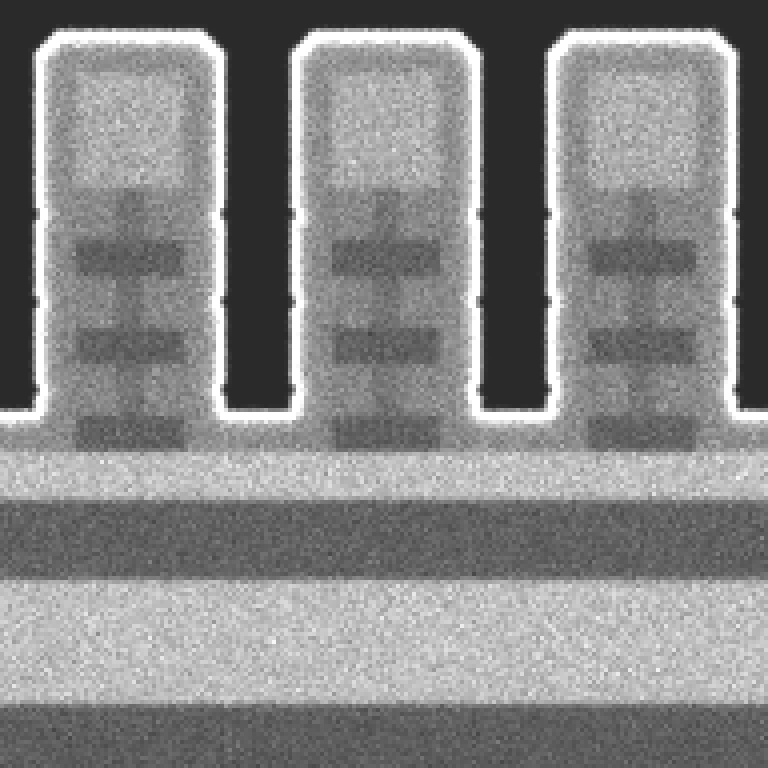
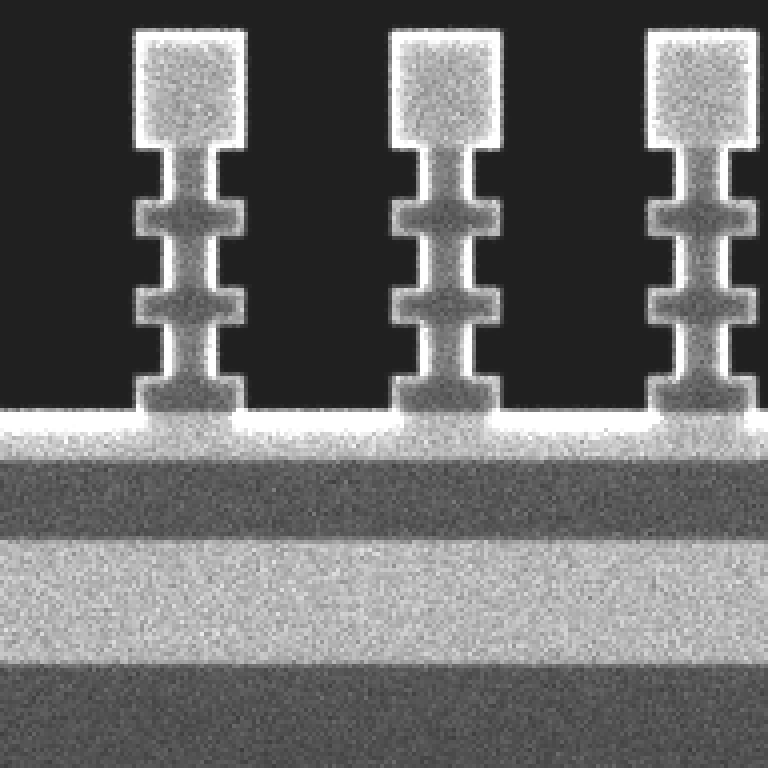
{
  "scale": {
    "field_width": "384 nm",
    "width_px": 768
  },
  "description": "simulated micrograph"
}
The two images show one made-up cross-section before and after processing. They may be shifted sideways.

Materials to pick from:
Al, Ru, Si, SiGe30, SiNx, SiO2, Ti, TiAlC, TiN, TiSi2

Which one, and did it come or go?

SiNx - removed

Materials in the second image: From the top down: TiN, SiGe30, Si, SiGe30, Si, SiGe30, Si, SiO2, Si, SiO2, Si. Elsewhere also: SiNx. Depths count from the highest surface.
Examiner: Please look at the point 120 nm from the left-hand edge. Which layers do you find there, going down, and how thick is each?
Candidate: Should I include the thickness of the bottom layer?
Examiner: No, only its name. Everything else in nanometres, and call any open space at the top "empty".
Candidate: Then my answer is TiN 58, empty 26, Si 18, empty 26, Si 18, empty 26, Si 18, SiO2 24, Si 40, SiO2 62, Si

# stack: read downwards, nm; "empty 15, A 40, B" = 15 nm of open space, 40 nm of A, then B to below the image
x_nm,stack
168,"empty 190, SiO2 24, Si 40, SiO2 62, Si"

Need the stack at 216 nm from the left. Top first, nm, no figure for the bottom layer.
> TiN 58, SiGe30 26, Si 18, SiGe30 26, Si 18, SiGe30 26, Si 18, SiO2 24, Si 40, SiO2 62, Si